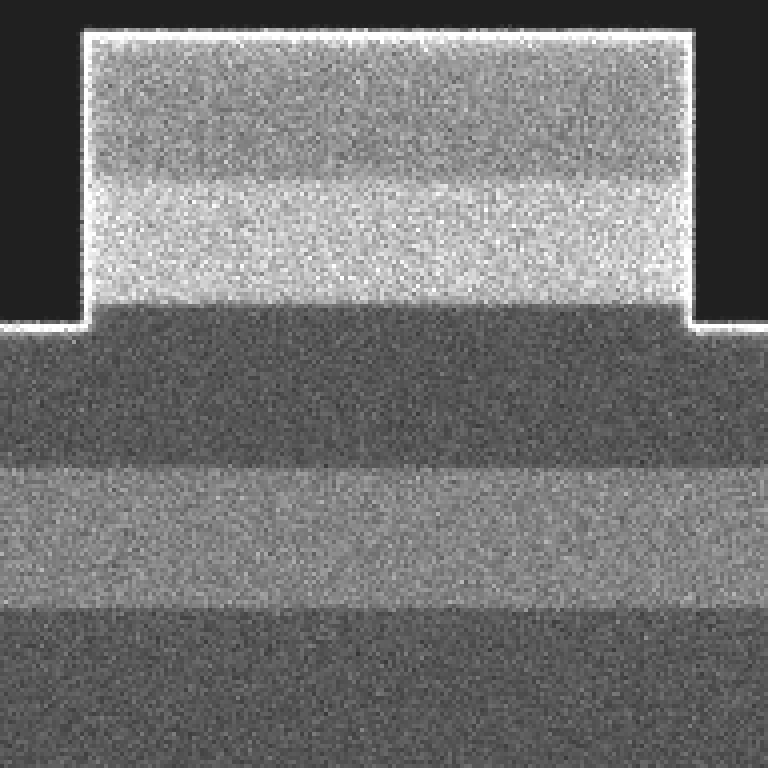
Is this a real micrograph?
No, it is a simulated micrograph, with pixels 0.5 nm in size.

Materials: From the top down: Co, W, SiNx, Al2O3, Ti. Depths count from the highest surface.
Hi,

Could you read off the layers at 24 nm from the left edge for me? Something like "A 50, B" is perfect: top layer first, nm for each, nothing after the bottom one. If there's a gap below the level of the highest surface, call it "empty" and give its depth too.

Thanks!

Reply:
empty 146, SiNx 72, Al2O3 70, Ti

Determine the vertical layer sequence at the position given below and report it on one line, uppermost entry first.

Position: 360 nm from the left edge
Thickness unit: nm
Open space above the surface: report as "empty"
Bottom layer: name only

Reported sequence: empty 146, SiNx 72, Al2O3 70, Ti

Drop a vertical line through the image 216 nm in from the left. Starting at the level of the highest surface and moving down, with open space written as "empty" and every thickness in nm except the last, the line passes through Co 74, W 62, SiNx 82, Al2O3 70, Ti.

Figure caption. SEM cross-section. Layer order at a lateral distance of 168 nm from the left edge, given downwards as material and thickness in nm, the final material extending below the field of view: Co 74, W 62, SiNx 82, Al2O3 70, Ti